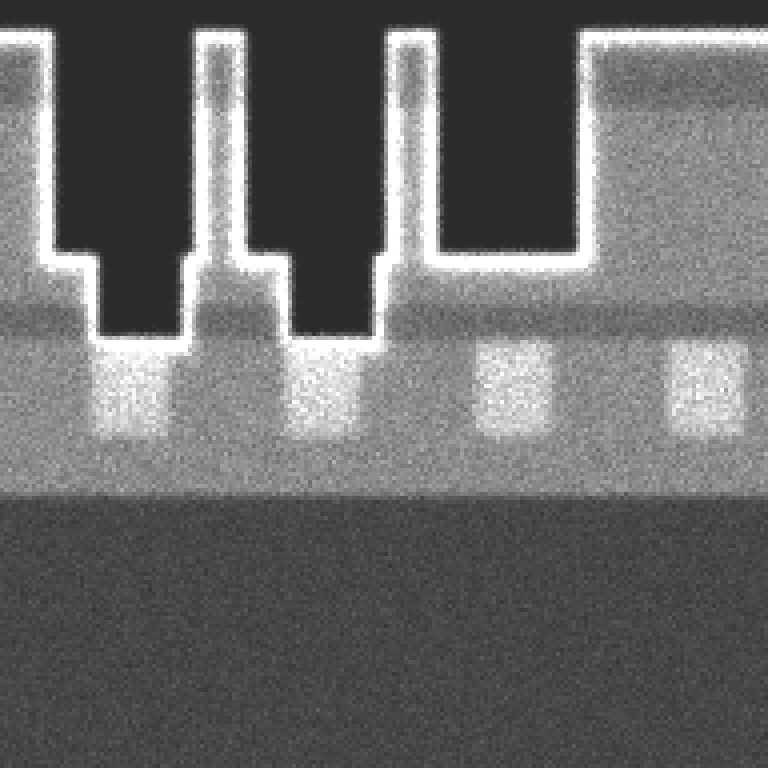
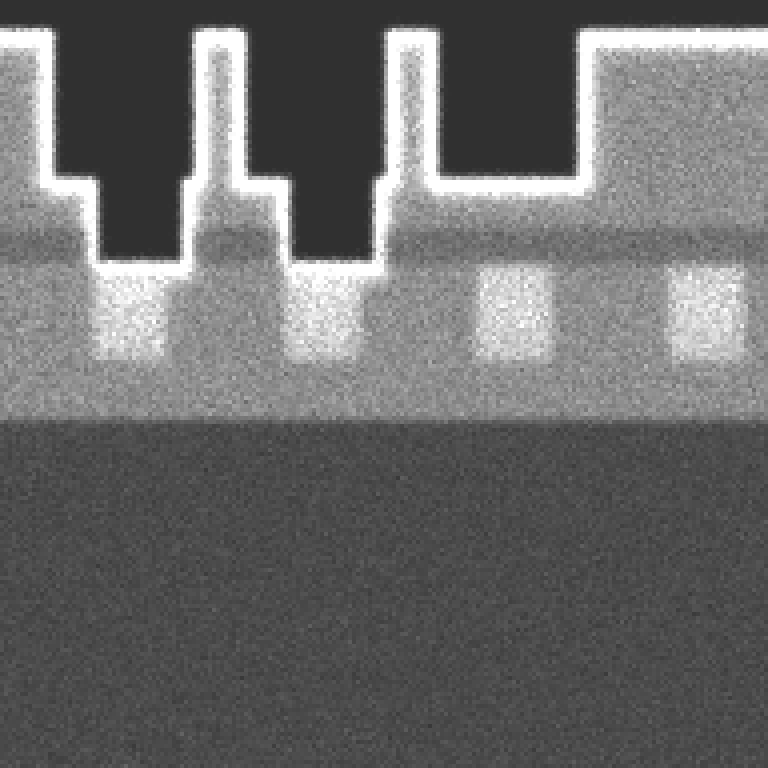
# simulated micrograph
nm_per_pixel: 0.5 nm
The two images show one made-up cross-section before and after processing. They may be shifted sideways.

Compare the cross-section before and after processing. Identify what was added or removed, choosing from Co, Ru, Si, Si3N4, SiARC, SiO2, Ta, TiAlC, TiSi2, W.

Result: SiARC removed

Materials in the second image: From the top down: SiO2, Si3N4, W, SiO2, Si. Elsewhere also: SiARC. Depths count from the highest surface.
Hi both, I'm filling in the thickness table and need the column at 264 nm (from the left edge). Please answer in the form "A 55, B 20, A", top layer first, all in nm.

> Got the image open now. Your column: empty 74, SiO2 24, Si3N4 18, W 48, SiO2 30, Si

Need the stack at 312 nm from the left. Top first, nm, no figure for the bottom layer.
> SiO2 98, Si3N4 18, SiO2 78, Si